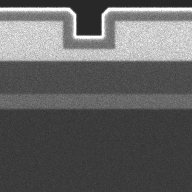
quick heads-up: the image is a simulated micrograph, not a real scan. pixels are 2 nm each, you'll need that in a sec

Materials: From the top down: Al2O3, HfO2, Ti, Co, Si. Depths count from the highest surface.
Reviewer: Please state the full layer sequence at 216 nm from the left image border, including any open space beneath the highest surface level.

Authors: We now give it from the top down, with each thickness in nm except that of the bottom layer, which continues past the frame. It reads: Al2O3 82, HfO2 24, Ti 66, Co 30, Si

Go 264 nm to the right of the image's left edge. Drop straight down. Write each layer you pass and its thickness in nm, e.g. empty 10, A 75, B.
Al2O3 26, HfO2 80, Ti 66, Co 30, Si